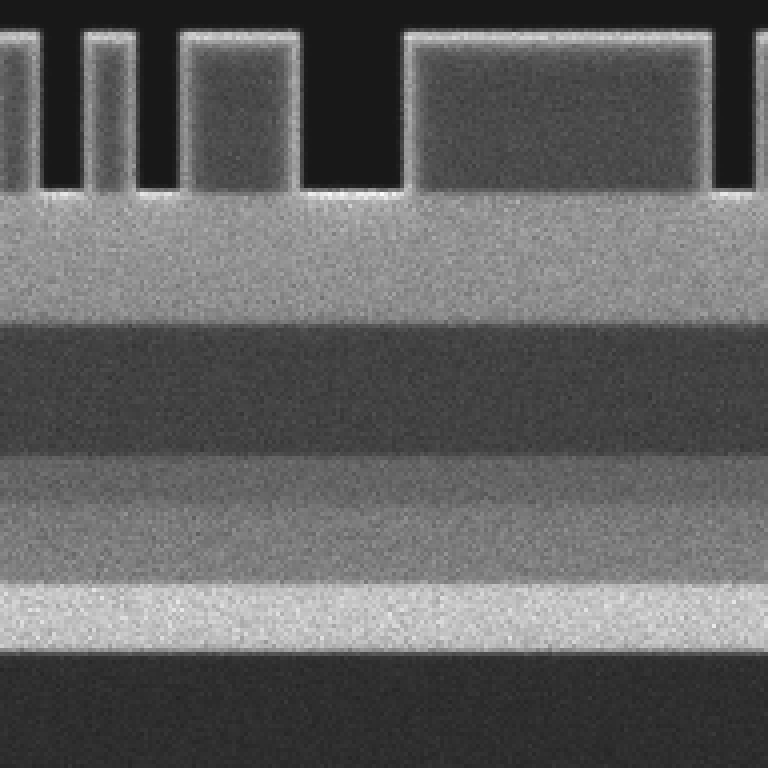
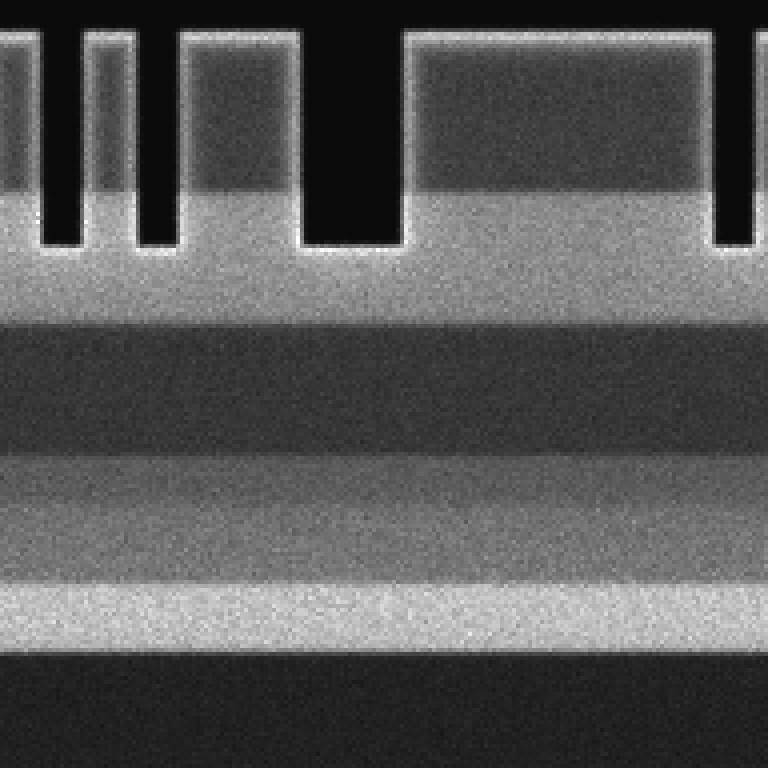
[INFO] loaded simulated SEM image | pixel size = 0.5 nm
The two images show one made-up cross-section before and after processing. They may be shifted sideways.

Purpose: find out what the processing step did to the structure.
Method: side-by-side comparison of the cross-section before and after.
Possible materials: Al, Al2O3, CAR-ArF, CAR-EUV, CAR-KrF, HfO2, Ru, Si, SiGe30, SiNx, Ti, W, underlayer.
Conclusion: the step removed W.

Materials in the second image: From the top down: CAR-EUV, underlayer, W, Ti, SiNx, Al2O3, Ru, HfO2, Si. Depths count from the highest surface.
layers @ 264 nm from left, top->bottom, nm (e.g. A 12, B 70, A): CAR-EUV 40, underlayer 40, W 66, Ti 18, SiNx 48, Al2O3 24, Ru 40, HfO2 34, Si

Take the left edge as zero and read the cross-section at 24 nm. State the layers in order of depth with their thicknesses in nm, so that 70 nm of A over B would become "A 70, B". empty 108, W 38, Ti 18, SiNx 48, Al2O3 24, Ru 40, HfO2 34, Si